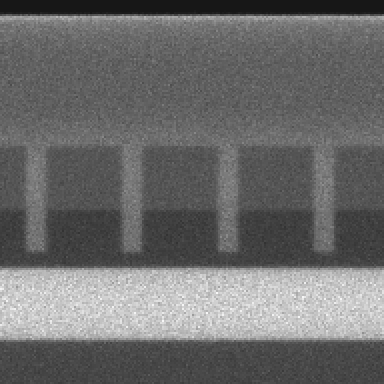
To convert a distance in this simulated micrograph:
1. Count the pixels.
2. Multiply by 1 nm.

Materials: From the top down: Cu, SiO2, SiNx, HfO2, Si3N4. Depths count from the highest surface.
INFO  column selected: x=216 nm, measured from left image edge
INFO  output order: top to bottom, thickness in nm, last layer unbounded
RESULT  Cu 130, SiO2 64, SiNx 58, HfO2 72, Si3N4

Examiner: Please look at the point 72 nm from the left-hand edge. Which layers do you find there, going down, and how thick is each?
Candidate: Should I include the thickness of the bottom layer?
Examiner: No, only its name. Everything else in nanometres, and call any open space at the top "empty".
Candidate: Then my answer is Cu 130, SiO2 64, SiNx 58, HfO2 72, Si3N4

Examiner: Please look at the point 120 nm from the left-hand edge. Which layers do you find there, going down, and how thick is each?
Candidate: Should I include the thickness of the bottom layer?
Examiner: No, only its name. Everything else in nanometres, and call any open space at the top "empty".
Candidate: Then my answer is Cu 130, SiO2 64, SiNx 58, HfO2 72, Si3N4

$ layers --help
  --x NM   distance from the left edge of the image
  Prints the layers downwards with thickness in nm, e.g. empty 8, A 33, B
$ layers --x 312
Cu 130, SiO2 64, SiNx 58, HfO2 72, Si3N4